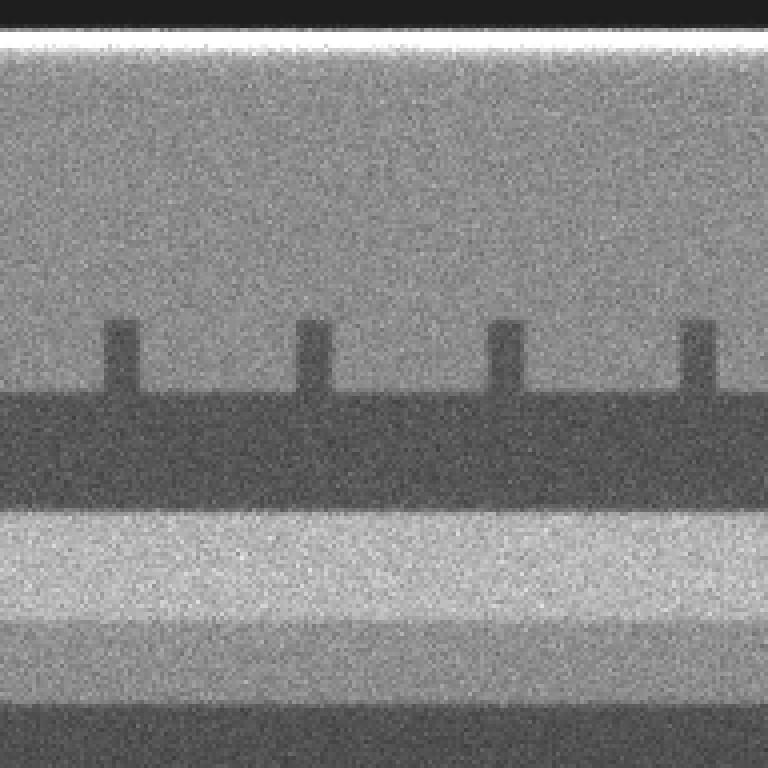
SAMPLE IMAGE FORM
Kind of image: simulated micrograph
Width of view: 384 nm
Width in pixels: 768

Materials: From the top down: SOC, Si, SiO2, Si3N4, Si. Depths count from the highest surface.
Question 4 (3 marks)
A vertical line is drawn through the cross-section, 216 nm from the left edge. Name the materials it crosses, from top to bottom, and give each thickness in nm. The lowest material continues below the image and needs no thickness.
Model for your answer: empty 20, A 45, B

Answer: SOC 180, Si 60, SiO2 54, Si3N4 42, Si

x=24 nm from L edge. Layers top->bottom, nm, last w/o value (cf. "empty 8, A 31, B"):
SOC 180, Si 60, SiO2 54, Si3N4 42, Si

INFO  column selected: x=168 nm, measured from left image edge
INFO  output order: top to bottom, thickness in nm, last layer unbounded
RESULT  SOC 180, Si 60, SiO2 54, Si3N4 42, Si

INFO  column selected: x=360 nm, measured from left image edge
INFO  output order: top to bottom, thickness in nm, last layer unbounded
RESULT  SOC 180, Si 60, SiO2 54, Si3N4 42, Si